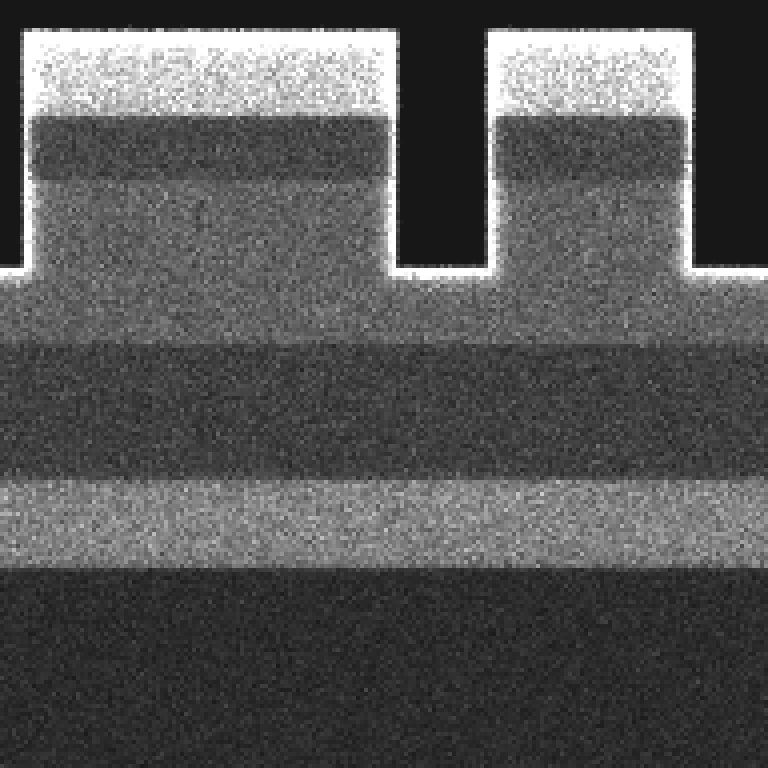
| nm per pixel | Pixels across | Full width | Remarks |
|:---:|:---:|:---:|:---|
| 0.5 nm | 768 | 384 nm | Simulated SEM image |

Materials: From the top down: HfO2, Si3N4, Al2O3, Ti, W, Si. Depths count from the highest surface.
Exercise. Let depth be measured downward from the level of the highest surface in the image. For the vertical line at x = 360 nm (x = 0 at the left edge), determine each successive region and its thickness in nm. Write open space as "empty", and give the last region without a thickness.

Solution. empty 118, Al2O3 38, Ti 68, W 44, Si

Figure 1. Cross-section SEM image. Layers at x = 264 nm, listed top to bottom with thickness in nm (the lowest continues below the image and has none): HfO2 42, Si3N4 32, Al2O3 82, Ti 68, W 44, Si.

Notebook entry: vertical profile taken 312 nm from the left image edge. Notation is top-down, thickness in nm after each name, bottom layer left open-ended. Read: HfO2 42, Si3N4 32, Al2O3 82, Ti 68, W 44, Si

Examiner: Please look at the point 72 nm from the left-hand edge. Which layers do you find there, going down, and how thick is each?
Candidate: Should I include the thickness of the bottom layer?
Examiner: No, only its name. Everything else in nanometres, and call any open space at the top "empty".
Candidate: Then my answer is HfO2 42, Si3N4 32, Al2O3 82, Ti 68, W 44, Si